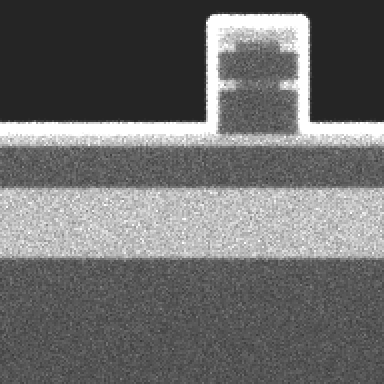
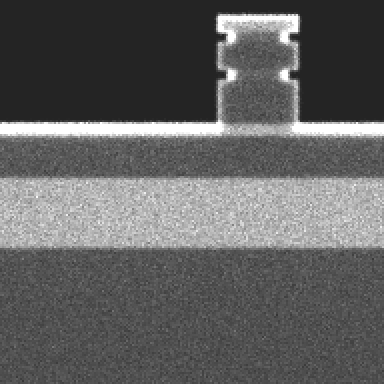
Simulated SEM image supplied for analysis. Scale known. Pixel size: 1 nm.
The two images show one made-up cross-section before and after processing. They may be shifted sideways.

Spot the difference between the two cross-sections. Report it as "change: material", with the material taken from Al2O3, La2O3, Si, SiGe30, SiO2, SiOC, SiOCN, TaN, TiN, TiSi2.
removed: Al2O3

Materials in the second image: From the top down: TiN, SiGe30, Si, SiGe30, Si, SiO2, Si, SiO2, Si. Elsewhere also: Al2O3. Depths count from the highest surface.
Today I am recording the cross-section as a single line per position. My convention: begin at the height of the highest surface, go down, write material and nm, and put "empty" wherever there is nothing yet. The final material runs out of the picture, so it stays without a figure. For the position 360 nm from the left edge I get empty 108, SiO2 12, Si 42, SiO2 70, Si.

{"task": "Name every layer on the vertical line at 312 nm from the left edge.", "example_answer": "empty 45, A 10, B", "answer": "empty 108, SiO2 12, Si 42, SiO2 70, Si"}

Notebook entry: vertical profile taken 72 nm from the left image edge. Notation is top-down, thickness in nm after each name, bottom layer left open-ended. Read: empty 108, SiO2 12, Si 42, SiO2 70, Si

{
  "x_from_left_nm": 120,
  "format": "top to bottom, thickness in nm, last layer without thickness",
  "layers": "empty 108, SiO2 12, Si 42, SiO2 70, Si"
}